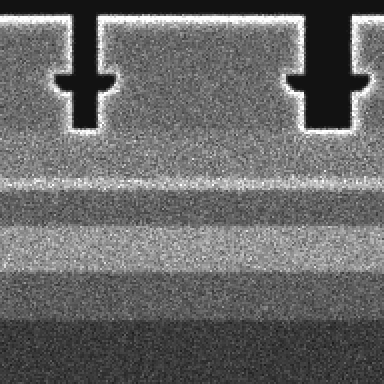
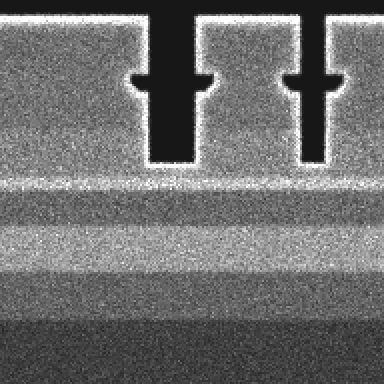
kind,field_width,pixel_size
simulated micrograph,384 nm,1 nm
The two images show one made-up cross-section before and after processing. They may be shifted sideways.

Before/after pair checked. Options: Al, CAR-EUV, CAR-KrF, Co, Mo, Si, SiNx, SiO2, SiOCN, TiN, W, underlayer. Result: removed TiN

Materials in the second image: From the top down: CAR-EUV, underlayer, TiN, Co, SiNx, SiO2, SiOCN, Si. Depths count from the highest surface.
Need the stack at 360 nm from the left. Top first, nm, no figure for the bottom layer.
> CAR-EUV 58, underlayer 56, TiN 48, Co 12, SiNx 36, SiO2 46, SiOCN 48, Si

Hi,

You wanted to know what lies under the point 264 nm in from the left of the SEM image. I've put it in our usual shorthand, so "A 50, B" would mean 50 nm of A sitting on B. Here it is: CAR-EUV 58, underlayer 56, TiN 48, Co 12, SiNx 36, SiO2 46, SiOCN 48, Si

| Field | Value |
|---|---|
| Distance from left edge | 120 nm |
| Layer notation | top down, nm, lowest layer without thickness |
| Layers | CAR-EUV 58, underlayer 56, TiN 48, Co 12, SiNx 36, SiO2 46, SiOCN 48, Si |